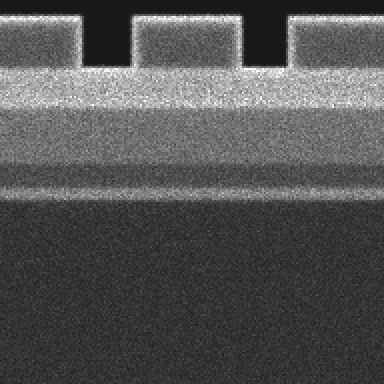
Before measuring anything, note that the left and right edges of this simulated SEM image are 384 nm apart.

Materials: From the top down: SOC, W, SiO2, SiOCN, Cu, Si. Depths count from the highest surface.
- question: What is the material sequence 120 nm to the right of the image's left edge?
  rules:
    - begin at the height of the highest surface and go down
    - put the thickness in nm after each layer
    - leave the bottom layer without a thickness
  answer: empty 52, W 40, SiO2 56, SiOCN 24, Cu 12, Si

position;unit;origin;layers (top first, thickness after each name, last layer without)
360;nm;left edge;SOC 52, W 40, SiO2 56, SiOCN 24, Cu 12, Si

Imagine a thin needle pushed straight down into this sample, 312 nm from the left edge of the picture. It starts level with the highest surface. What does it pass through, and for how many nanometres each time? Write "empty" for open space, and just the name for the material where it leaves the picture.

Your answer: SOC 52, W 40, SiO2 56, SiOCN 24, Cu 12, Si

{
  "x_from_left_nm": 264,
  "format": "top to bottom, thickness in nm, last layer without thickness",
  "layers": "empty 52, W 40, SiO2 56, SiOCN 24, Cu 12, Si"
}